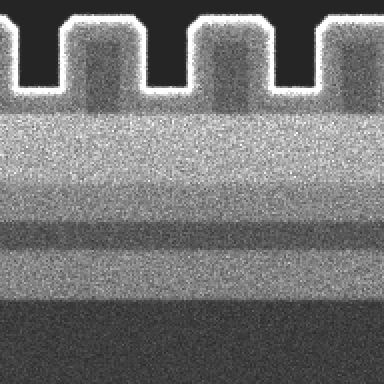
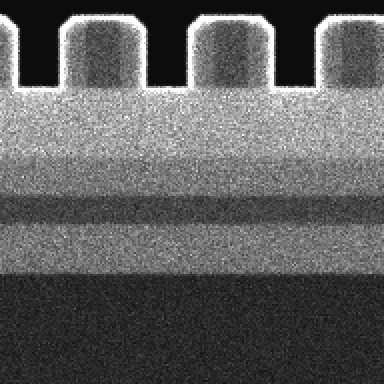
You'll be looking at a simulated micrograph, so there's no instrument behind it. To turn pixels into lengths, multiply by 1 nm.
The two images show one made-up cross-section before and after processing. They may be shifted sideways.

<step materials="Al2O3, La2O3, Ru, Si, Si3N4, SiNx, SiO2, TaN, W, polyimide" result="removed SiO2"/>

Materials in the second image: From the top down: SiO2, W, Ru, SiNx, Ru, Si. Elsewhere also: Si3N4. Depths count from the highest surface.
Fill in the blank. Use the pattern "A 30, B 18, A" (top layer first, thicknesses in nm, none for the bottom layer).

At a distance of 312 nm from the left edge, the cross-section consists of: empty 72, W 70, Ru 38, SiNx 28, Ru 50, Si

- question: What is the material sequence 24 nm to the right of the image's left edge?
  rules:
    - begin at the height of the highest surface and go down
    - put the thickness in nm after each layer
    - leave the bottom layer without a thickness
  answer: empty 72, W 70, Ru 38, SiNx 28, Ru 50, Si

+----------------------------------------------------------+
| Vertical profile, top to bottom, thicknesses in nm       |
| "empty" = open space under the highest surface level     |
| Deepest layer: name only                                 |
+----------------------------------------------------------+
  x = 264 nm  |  empty 4, SiO2 68, W 70, Ru 38, SiNx 28, Ru 50, Si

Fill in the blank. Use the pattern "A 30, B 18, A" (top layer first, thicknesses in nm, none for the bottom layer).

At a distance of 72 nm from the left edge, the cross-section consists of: SiO2 72, W 70, Ru 38, SiNx 28, Ru 50, Si